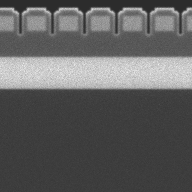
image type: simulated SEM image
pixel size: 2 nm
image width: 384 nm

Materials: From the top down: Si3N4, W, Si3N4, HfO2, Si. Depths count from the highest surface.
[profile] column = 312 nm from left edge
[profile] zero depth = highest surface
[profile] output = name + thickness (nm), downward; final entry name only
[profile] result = Si3N4 16, W 30, Si3N4 52, HfO2 64, Si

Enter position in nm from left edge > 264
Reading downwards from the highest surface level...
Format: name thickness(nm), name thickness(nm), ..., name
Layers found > Si3N4 16, W 30, Si3N4 52, HfO2 64, Si